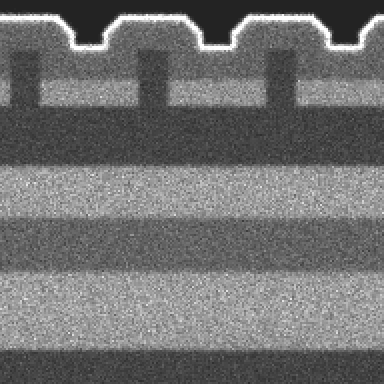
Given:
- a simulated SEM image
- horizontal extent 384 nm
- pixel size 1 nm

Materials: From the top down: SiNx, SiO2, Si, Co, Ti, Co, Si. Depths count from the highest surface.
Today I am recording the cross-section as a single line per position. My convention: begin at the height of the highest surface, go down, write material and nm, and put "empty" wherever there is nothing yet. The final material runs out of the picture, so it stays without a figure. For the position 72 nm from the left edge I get empty 16, SiNx 48, SiO2 26, Si 60, Co 52, Ti 54, Co 78, Si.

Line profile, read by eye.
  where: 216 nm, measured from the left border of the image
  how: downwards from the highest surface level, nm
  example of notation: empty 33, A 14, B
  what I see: empty 30, SiNx 34, SiO2 26, Si 60, Co 52, Ti 54, Co 78, Si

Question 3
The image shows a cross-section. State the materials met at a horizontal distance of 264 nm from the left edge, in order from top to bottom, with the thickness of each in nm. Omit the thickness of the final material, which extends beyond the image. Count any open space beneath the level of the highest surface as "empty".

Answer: SiNx 64, SiO2 26, Si 60, Co 52, Ti 54, Co 78, Si